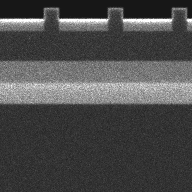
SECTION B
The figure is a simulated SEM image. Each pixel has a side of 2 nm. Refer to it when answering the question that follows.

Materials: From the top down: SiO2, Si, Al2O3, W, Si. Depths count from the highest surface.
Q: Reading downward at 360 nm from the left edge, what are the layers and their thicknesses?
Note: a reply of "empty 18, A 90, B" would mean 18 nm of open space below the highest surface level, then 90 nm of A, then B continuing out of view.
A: Si 106, Al2O3 44, W 42, Si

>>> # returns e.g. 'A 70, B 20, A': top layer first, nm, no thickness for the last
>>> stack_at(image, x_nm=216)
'Si 106, Al2O3 44, W 42, Si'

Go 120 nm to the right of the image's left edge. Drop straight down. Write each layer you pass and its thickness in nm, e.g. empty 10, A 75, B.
empty 22, SiO2 24, Si 60, Al2O3 44, W 42, Si